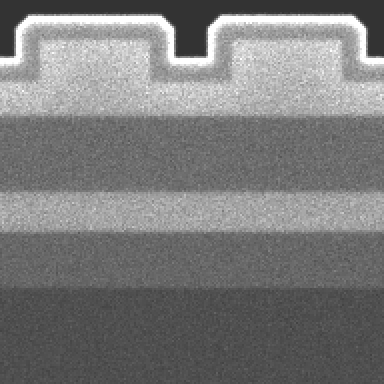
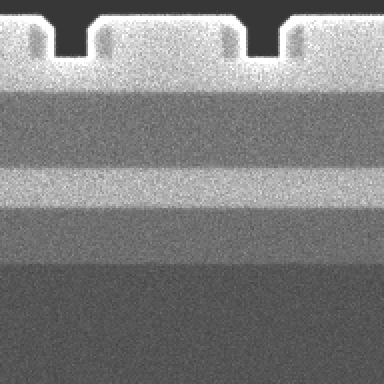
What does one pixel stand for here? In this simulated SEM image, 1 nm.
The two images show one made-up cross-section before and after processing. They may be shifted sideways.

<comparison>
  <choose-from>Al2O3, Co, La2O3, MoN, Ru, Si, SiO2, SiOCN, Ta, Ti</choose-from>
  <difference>SiO2 removed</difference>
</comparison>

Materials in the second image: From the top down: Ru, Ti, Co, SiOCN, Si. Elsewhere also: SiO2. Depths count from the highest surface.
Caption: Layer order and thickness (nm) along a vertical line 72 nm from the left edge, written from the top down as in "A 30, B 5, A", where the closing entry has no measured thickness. empty 42, Ru 34, Ti 76, Co 40, SiOCN 56, Si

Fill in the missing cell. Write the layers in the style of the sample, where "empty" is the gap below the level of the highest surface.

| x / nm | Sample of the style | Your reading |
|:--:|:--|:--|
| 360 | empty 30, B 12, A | Ru 76, Ti 76, Co 40, SiOCN 56, Si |